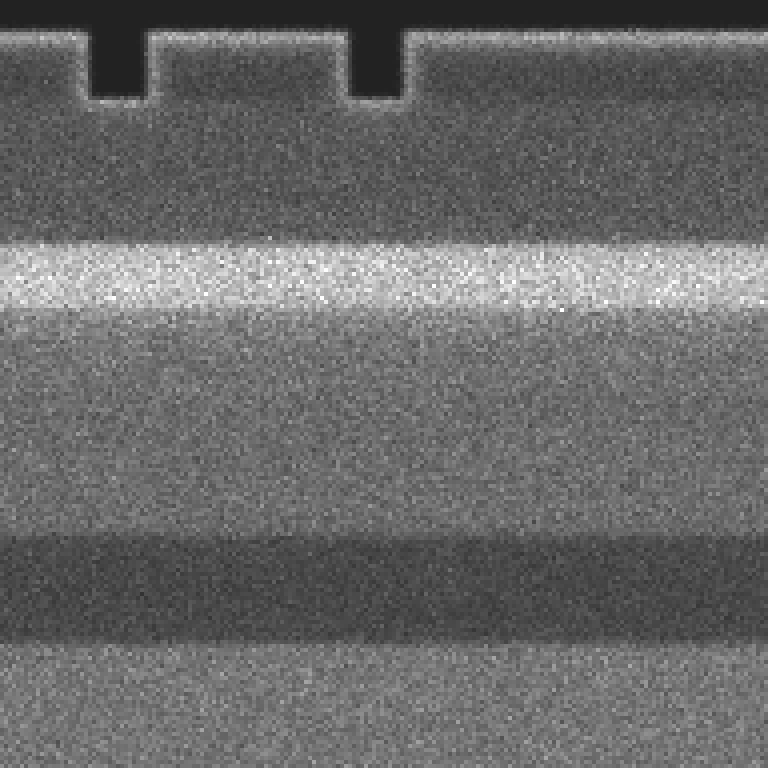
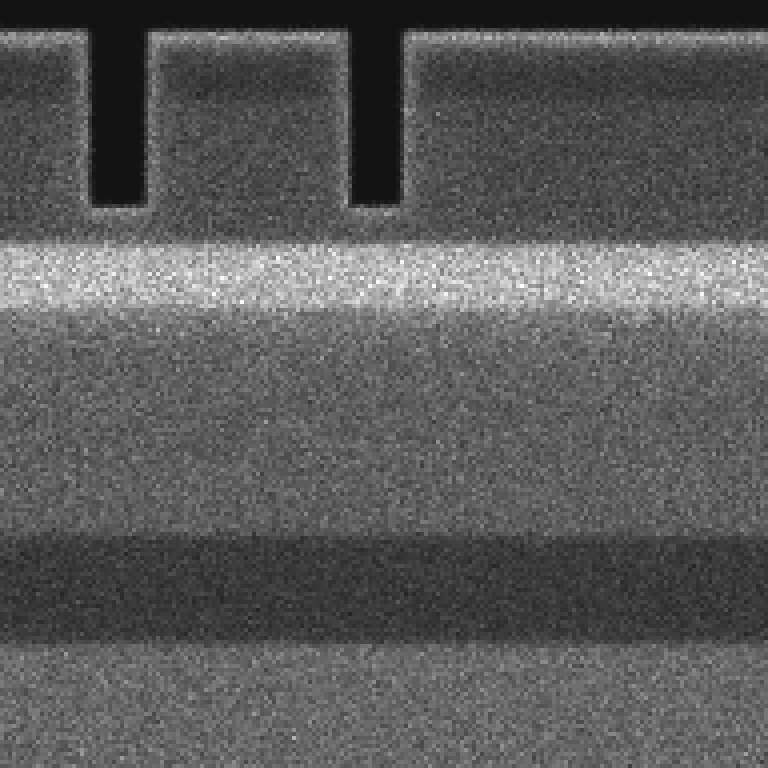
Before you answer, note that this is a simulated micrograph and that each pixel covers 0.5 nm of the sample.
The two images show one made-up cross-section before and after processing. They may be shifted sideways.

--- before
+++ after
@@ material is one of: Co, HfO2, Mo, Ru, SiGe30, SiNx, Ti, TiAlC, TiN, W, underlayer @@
TiN removed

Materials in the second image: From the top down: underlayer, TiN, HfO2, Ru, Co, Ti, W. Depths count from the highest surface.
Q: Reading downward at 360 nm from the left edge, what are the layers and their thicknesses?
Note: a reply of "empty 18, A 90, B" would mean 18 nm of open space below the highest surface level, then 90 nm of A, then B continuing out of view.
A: underlayer 34, TiN 72, HfO2 32, Ru 42, Co 72, Ti 54, W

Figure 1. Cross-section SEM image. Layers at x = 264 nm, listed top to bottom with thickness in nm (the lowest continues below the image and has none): underlayer 34, TiN 72, HfO2 32, Ru 42, Co 72, Ti 54, W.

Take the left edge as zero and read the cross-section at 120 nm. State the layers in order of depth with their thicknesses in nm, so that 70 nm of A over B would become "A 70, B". underlayer 34, TiN 72, HfO2 32, Ru 42, Co 72, Ti 54, W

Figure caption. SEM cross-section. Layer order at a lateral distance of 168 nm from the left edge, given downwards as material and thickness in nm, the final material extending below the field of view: underlayer 34, TiN 72, HfO2 32, Ru 42, Co 72, Ti 54, W